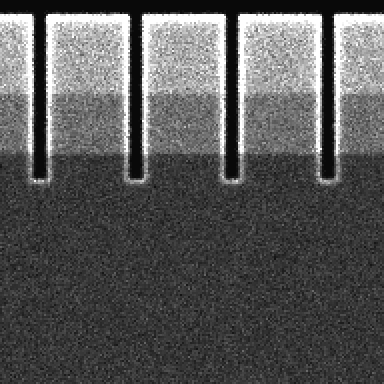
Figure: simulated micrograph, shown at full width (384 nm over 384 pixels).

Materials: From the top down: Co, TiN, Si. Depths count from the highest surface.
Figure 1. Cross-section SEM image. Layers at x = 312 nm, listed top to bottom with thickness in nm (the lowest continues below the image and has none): Co 78, TiN 60, Si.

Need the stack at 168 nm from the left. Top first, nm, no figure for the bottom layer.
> Co 78, TiN 60, Si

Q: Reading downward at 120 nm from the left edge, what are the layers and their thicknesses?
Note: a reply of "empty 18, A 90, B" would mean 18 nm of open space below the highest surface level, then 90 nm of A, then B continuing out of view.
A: Co 78, TiN 60, Si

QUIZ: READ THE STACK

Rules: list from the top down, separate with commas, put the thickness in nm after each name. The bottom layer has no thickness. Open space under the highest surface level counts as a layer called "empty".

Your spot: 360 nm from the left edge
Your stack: Co 78, TiN 60, Si